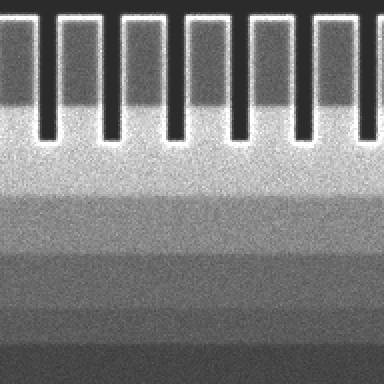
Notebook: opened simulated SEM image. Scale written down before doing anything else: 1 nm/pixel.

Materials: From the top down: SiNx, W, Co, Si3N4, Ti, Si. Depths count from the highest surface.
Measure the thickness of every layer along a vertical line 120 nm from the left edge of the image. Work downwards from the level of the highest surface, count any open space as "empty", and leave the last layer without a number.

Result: empty 126, W 54, Co 58, Si3N4 54, Ti 36, Si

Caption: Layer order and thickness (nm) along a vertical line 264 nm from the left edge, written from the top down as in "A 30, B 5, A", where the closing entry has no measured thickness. SiNx 90, W 90, Co 58, Si3N4 54, Ti 36, Si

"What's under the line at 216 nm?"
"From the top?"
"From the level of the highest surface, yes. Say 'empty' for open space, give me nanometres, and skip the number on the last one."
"SiNx 90, W 90, Co 58, Si3N4 54, Ti 36, Si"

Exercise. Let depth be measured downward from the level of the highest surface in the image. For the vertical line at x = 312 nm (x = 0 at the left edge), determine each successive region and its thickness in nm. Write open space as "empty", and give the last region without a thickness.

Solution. empty 126, W 54, Co 58, Si3N4 54, Ti 36, Si